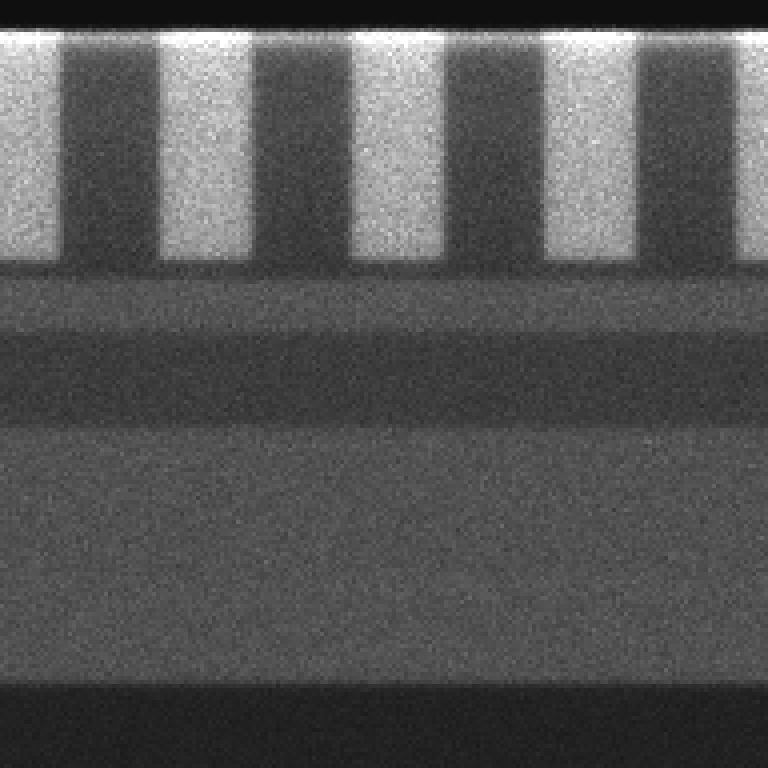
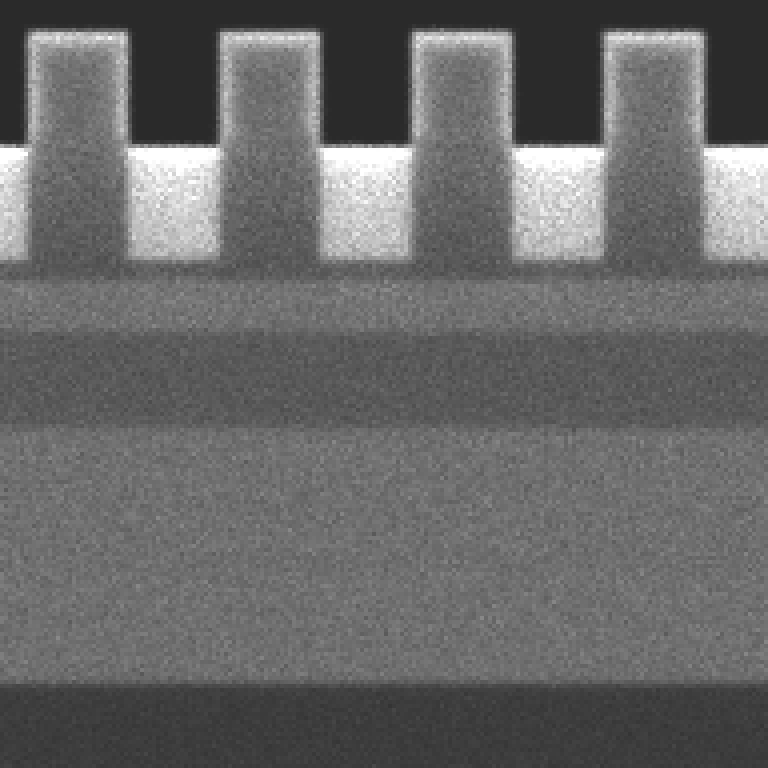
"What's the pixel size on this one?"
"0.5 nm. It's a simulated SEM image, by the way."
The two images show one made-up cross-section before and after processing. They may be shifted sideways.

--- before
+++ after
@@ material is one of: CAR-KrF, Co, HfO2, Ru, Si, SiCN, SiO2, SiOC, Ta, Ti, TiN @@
HfO2 removed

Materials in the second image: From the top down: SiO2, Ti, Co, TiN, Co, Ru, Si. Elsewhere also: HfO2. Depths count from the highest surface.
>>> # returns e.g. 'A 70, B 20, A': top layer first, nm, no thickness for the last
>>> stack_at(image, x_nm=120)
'SiO2 52, Ti 72, Co 26, TiN 48, Co 74, Ru 54, Si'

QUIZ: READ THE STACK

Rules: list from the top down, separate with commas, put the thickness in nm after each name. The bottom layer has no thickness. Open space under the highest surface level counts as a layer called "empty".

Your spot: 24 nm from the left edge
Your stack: SiO2 52, Ti 72, Co 26, TiN 48, Co 74, Ru 54, Si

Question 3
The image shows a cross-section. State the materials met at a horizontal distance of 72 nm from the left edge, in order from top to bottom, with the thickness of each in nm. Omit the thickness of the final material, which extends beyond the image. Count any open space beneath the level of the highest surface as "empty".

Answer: empty 58, HfO2 56, Ti 10, Co 26, TiN 48, Co 74, Ru 54, Si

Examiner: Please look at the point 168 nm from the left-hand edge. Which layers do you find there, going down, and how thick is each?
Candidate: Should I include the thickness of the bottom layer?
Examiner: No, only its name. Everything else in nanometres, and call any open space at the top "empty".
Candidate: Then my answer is empty 58, HfO2 56, Ti 10, Co 26, TiN 48, Co 74, Ru 54, Si